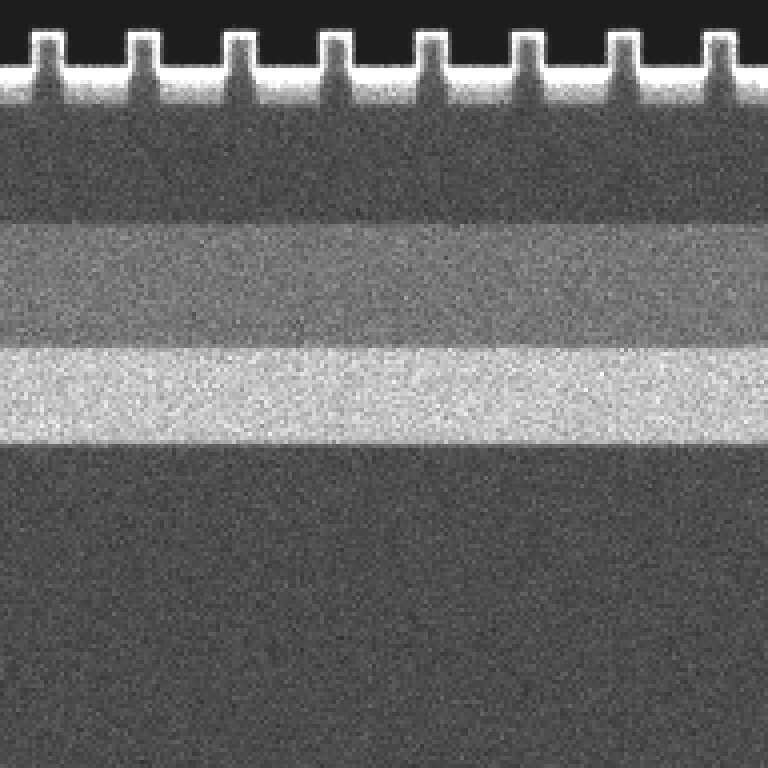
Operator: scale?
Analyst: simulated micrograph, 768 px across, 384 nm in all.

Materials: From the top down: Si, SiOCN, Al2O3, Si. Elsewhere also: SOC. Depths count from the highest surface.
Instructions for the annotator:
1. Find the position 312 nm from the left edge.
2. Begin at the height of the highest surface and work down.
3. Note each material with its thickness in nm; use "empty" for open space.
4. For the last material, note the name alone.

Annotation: Si 96, SiOCN 62, Al2O3 48, Si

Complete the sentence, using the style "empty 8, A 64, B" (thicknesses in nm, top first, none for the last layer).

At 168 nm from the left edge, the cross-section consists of Si 96, SiOCN 62, Al2O3 48, Si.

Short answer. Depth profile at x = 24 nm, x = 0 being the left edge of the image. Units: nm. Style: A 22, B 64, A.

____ Si 96, SiOCN 62, Al2O3 48, Si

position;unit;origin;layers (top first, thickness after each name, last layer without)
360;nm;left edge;Si 96, SiOCN 62, Al2O3 48, Si